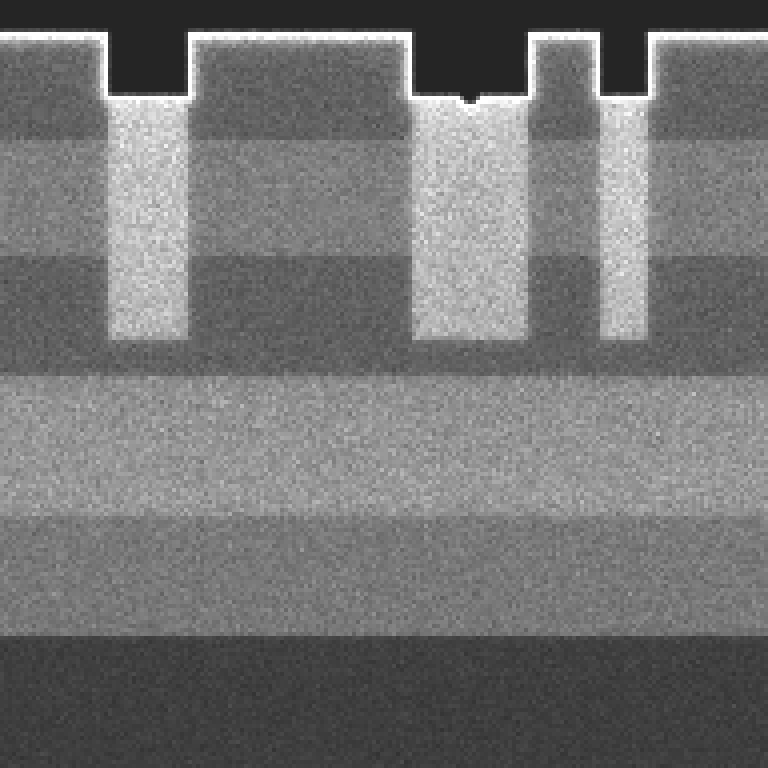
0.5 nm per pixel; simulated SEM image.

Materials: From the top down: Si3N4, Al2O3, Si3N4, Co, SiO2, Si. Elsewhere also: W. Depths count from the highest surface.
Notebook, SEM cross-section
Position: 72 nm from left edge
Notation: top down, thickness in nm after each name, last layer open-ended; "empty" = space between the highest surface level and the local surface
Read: empty 32, W 122, Si3N4 18, Co 70, SiO2 60, Si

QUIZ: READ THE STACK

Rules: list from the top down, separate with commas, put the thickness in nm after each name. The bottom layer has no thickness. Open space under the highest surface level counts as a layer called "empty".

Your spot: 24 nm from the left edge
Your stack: Si3N4 54, Al2O3 58, Si3N4 60, Co 70, SiO2 60, Si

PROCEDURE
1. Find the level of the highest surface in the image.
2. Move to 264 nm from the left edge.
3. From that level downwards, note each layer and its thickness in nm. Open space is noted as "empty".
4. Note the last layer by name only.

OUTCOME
Si3N4 54, Al2O3 58, Si3N4 60, Co 70, SiO2 60, Si